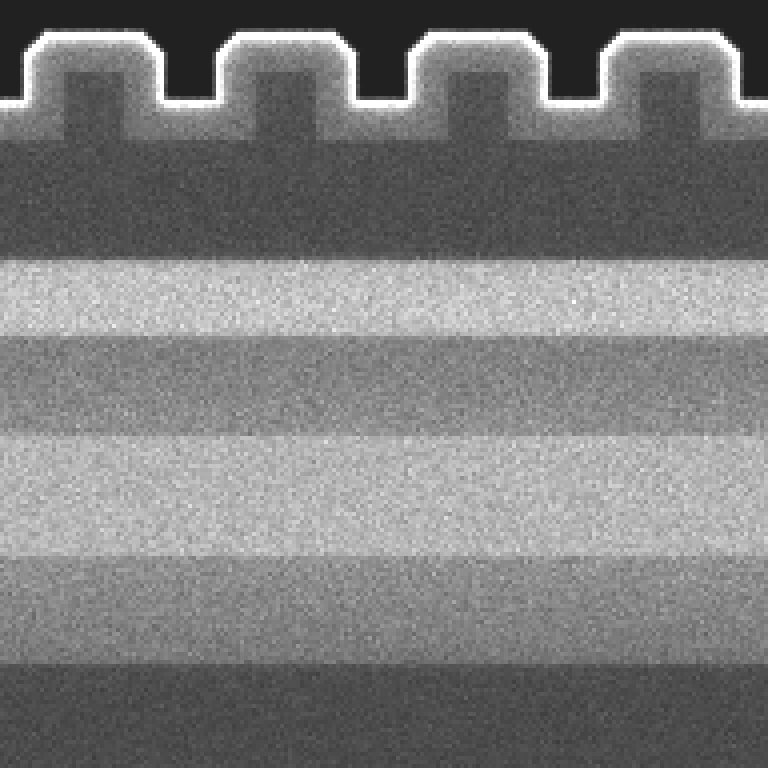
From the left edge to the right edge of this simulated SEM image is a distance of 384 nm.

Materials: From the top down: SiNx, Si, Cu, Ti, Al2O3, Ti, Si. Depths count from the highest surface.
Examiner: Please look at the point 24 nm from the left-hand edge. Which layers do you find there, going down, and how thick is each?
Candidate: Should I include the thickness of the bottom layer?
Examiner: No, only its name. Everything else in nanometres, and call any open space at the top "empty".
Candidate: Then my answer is SiNx 54, Si 60, Cu 38, Ti 50, Al2O3 60, Ti 54, Si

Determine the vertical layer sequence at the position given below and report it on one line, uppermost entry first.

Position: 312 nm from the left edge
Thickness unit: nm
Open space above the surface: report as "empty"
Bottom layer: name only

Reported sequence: SiNx 54, Si 60, Cu 38, Ti 50, Al2O3 60, Ti 54, Si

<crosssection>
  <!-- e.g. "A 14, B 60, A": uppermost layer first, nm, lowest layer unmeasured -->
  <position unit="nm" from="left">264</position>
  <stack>empty 2, SiNx 52, Si 60, Cu 38, Ti 50, Al2O3 60, Ti 54, Si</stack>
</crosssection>